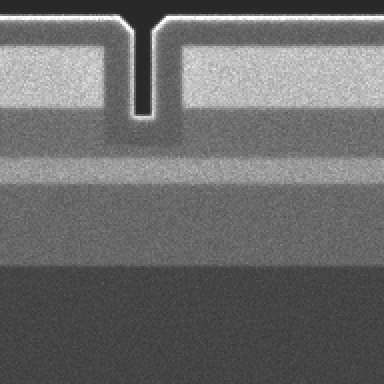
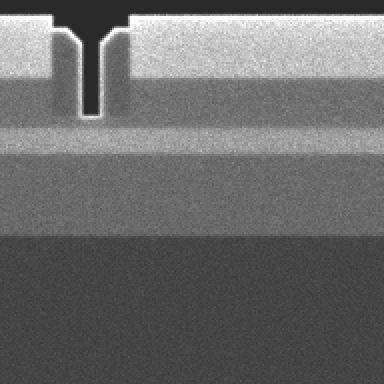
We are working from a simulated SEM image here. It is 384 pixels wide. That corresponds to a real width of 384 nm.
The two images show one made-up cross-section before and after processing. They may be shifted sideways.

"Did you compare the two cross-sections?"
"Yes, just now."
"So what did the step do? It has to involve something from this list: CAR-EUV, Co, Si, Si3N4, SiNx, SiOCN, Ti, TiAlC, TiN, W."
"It removed SiNx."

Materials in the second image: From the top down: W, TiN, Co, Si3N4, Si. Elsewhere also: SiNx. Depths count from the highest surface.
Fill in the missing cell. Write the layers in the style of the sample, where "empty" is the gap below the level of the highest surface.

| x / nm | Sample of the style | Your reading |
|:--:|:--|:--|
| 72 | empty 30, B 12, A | empty 18, SiNx 82, TiN 12, Co 26, Si3N4 82, Si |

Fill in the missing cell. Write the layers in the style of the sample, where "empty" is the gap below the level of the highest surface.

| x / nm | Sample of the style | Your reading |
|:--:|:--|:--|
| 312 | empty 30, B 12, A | W 62, TiN 50, Co 26, Si3N4 82, Si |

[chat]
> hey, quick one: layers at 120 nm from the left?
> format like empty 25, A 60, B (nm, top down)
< empty 12, SiNx 88, TiN 12, Co 26, Si3N4 82, Si